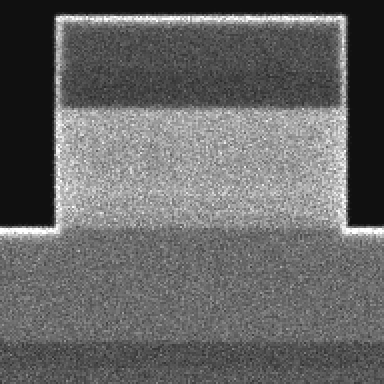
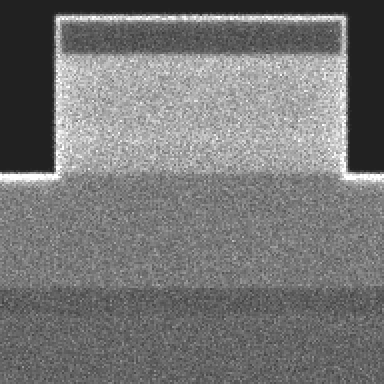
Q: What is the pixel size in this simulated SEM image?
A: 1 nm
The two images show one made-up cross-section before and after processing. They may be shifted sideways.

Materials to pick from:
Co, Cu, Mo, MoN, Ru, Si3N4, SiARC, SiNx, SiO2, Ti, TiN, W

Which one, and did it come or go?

SiARC - removed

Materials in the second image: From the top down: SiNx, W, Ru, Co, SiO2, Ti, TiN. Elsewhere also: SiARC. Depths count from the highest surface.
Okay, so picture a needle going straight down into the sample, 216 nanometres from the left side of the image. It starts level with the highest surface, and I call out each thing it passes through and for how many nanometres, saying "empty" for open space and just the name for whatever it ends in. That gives SiNx 38, W 90, Ru 16, Co 14, SiO2 114, Ti 26, TiN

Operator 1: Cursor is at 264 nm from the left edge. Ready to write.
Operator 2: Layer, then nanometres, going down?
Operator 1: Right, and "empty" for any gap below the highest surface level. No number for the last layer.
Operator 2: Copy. SiNx 38, W 90, Ru 16, Co 14, SiO2 114, Ti 26, TiN